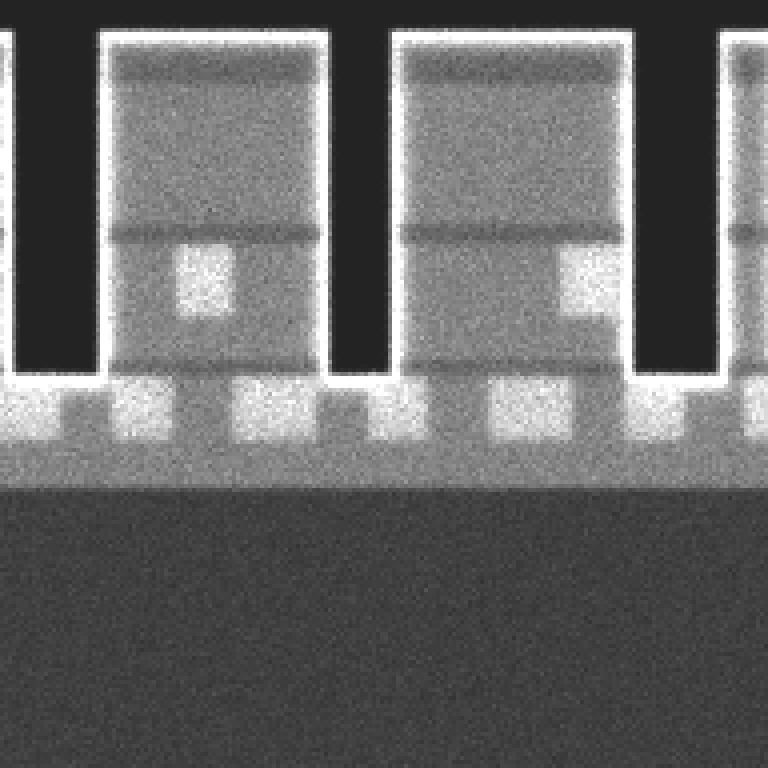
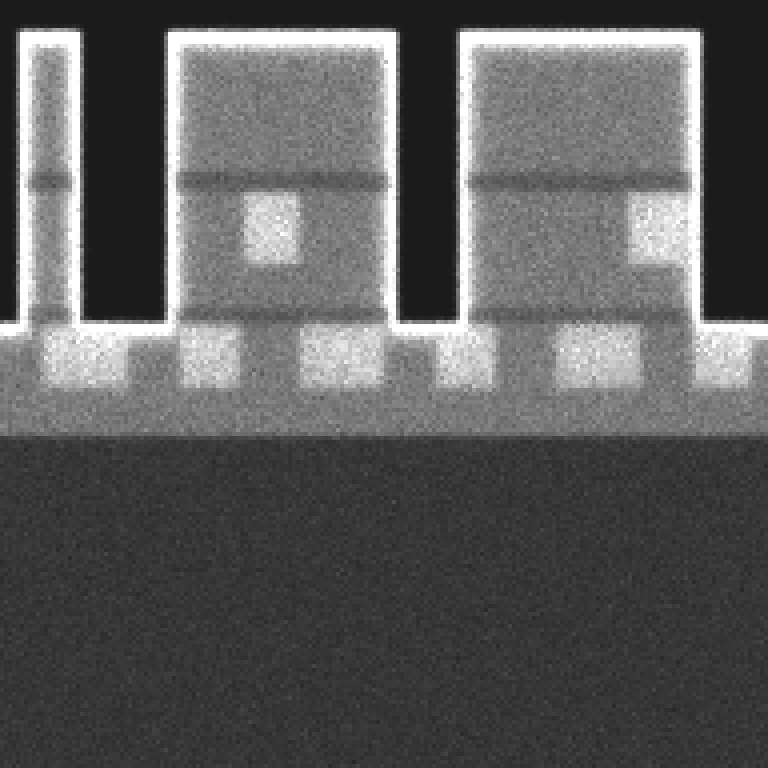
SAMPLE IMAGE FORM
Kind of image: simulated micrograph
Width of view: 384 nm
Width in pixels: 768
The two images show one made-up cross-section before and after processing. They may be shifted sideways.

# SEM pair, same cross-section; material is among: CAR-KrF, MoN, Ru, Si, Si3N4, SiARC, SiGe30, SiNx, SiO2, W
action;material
removed;SiARC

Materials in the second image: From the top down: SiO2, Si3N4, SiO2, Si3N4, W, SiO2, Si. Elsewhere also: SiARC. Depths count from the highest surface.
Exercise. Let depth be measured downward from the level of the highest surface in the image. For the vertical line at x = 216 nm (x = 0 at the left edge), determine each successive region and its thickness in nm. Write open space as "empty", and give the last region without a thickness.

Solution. empty 146, SiO2 56, Si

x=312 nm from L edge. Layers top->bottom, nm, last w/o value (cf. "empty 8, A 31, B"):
SiO2 70, Si3N4 10, SiO2 58, Si3N4 8, W 32, SiO2 24, Si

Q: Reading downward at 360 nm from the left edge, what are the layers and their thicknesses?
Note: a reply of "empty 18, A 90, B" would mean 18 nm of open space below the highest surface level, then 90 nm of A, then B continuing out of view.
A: empty 146, W 32, SiO2 24, Si